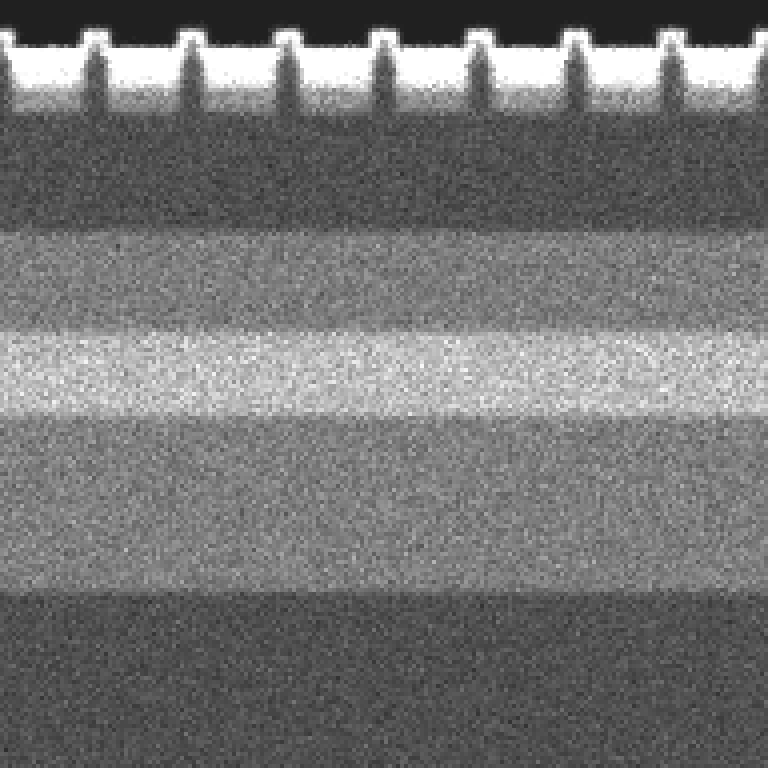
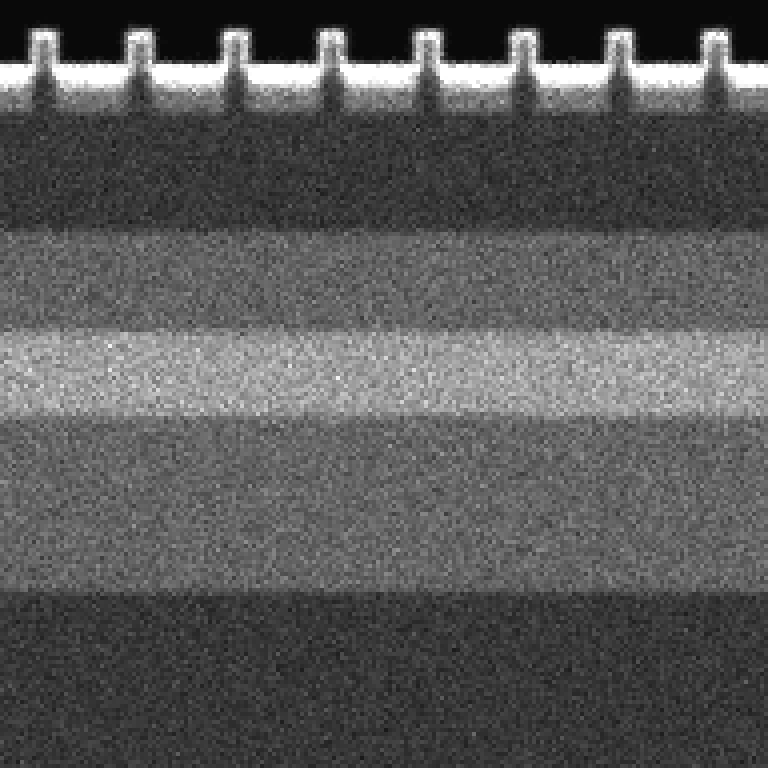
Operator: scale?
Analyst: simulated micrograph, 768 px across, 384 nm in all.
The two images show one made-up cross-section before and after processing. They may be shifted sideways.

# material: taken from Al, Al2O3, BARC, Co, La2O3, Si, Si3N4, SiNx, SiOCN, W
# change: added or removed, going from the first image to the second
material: W
change: removed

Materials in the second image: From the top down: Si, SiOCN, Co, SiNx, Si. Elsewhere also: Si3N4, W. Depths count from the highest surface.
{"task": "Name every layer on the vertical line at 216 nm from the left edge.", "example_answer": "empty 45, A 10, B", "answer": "Si 100, SiOCN 50, Co 42, SiNx 88, Si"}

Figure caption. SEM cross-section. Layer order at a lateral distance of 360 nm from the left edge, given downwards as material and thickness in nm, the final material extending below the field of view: Si 100, SiOCN 50, Co 42, SiNx 88, Si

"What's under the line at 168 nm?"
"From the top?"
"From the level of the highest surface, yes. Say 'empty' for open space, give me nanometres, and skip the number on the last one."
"Si 100, SiOCN 50, Co 42, SiNx 88, Si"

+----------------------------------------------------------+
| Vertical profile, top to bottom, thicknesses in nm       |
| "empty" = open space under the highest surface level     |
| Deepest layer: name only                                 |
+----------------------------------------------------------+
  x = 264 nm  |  Si 100, SiOCN 50, Co 42, SiNx 88, Si